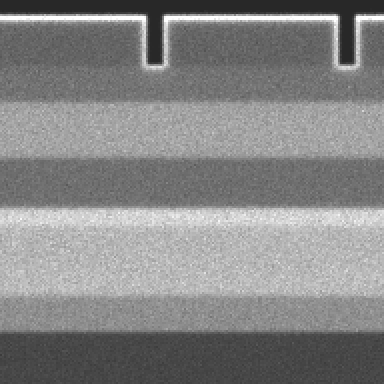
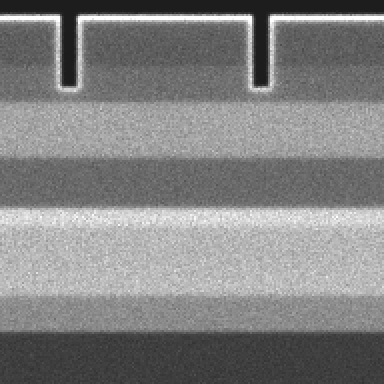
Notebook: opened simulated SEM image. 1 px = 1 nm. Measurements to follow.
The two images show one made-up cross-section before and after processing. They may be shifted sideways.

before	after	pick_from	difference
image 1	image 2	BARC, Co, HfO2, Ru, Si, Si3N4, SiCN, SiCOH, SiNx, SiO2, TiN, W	TiN removed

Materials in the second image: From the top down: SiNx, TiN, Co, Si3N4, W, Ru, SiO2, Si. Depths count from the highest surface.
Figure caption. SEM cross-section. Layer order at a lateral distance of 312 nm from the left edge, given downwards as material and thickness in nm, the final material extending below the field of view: SiNx 50, TiN 36, Co 56, Si3N4 50, W 18, Ru 70, SiO2 36, Si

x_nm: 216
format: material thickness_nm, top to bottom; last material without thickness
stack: SiNx 50, TiN 36, Co 56, Si3N4 50, W 18, Ru 70, SiO2 36, Si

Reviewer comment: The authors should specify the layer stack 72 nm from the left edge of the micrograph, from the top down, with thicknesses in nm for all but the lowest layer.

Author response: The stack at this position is empty 72, TiN 14, Co 56, Si3N4 50, W 18, Ru 70, SiO2 36, Si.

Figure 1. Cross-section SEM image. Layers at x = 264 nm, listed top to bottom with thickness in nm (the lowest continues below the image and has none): empty 72, TiN 14, Co 56, Si3N4 50, W 18, Ru 70, SiO2 36, Si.